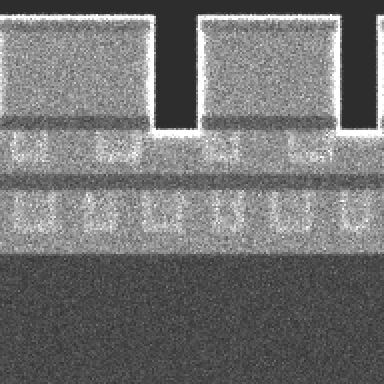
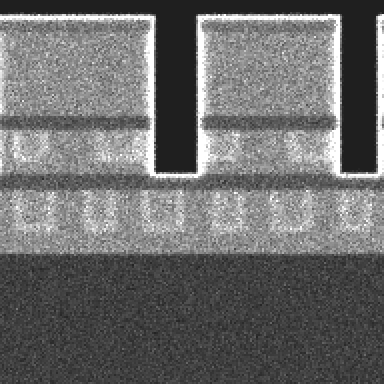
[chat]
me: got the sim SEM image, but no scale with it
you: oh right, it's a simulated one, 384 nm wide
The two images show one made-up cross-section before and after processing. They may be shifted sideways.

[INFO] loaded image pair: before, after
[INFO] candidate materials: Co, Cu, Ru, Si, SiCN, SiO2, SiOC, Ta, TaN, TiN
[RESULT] removed SiO2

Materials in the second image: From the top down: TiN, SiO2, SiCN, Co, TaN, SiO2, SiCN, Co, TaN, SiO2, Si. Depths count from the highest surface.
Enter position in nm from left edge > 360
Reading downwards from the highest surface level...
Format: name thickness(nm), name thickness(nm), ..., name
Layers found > empty 158, SiCN 16, Co 34, TaN 8, SiO2 22, Si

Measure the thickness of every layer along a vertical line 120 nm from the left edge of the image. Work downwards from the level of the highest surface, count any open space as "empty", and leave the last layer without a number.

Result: TiN 16, SiO2 84, SiCN 14, Co 24, TaN 8, SiO2 12, SiCN 16, SiO2 64, Si